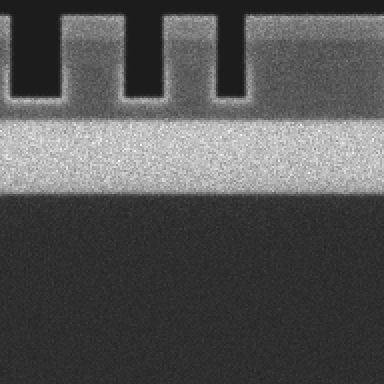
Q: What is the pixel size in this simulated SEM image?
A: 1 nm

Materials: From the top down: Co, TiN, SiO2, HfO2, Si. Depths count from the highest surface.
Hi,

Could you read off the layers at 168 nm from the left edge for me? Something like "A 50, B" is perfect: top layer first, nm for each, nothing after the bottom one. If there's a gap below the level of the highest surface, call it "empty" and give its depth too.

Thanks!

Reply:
Co 24, TiN 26, SiO2 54, HfO2 74, Si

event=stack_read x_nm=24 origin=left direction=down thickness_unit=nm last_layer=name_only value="empty 82, SiO2 22, HfO2 74, Si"